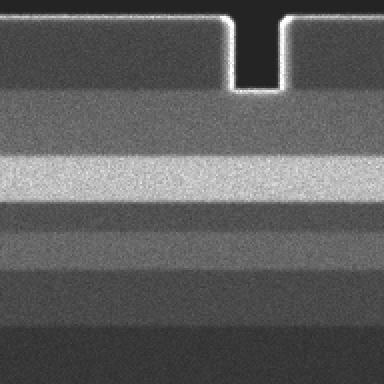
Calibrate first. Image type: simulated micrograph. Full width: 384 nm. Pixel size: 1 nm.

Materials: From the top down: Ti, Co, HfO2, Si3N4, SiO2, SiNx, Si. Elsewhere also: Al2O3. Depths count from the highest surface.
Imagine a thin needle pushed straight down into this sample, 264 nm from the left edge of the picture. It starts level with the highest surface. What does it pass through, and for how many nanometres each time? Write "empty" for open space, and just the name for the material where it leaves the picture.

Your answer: empty 74, Co 66, HfO2 46, Si3N4 30, SiO2 38, SiNx 56, Si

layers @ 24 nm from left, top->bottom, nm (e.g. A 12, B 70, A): Ti 74, Co 66, HfO2 46, Si3N4 30, SiO2 38, SiNx 56, Si